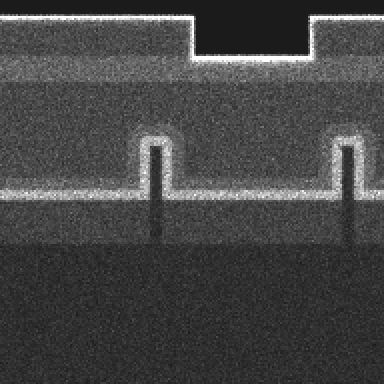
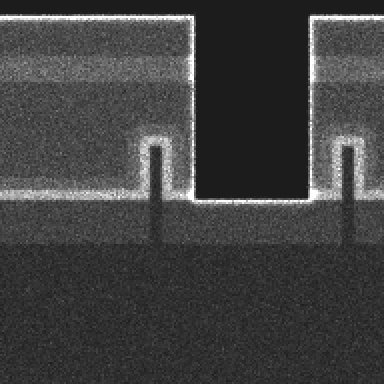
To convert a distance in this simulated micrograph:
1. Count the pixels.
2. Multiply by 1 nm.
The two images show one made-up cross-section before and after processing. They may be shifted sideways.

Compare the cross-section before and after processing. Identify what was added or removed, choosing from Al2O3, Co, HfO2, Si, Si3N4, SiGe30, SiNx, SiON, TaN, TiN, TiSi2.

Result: Al2O3 and Co and HfO2 and TiN removed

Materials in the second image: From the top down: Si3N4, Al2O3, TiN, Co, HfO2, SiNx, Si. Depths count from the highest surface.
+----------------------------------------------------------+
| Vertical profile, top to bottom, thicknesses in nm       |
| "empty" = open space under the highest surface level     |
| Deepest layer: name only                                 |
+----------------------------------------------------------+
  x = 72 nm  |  Si3N4 40, Al2O3 26, TiN 96, Co 12, HfO2 10, SiNx 44, Si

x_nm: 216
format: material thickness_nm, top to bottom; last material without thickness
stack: empty 184, SiNx 44, Si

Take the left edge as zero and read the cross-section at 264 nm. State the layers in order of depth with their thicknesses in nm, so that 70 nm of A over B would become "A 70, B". empty 184, SiNx 44, Si